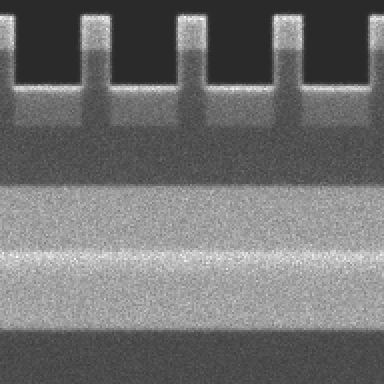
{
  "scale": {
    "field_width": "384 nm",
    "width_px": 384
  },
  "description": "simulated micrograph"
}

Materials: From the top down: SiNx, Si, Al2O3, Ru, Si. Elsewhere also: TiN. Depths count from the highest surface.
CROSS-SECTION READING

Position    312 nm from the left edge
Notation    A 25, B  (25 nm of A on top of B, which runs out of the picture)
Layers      empty 70, SiNx 40, Si 60, Al2O3 66, Ru 78, Si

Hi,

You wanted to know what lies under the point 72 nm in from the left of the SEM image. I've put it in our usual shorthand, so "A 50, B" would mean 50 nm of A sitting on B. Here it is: empty 70, SiNx 40, Si 60, Al2O3 66, Ru 78, Si